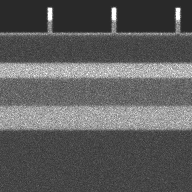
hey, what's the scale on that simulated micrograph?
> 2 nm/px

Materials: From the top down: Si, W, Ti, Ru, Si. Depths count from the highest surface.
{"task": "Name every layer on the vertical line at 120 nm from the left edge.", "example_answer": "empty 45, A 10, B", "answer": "empty 50, Si 60, W 30, Ti 56, Ru 48, Si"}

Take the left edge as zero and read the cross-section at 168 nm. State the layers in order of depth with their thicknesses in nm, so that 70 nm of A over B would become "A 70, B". empty 50, Si 60, W 30, Ti 56, Ru 48, Si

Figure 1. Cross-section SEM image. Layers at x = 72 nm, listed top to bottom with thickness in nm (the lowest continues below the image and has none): empty 50, Si 60, W 30, Ti 56, Ru 48, Si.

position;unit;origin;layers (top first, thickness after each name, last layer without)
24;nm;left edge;empty 50, Si 60, W 30, Ti 56, Ru 48, Si